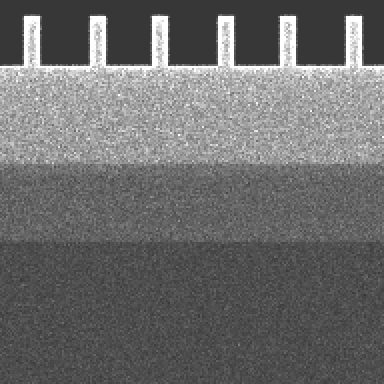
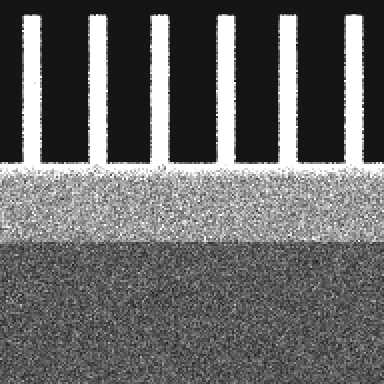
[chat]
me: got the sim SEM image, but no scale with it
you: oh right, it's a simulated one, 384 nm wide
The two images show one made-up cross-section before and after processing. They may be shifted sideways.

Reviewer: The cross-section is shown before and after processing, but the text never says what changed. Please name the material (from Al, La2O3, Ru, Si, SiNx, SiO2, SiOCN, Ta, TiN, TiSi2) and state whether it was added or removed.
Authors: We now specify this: Ru, removed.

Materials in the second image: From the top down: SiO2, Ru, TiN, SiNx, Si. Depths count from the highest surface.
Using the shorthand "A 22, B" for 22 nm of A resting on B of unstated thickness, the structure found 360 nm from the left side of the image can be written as SiO2 50, Ru 98, TiN 12, SiNx 66, Si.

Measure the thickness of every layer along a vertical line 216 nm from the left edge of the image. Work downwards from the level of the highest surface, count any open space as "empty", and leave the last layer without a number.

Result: empty 148, TiN 12, SiNx 66, Si